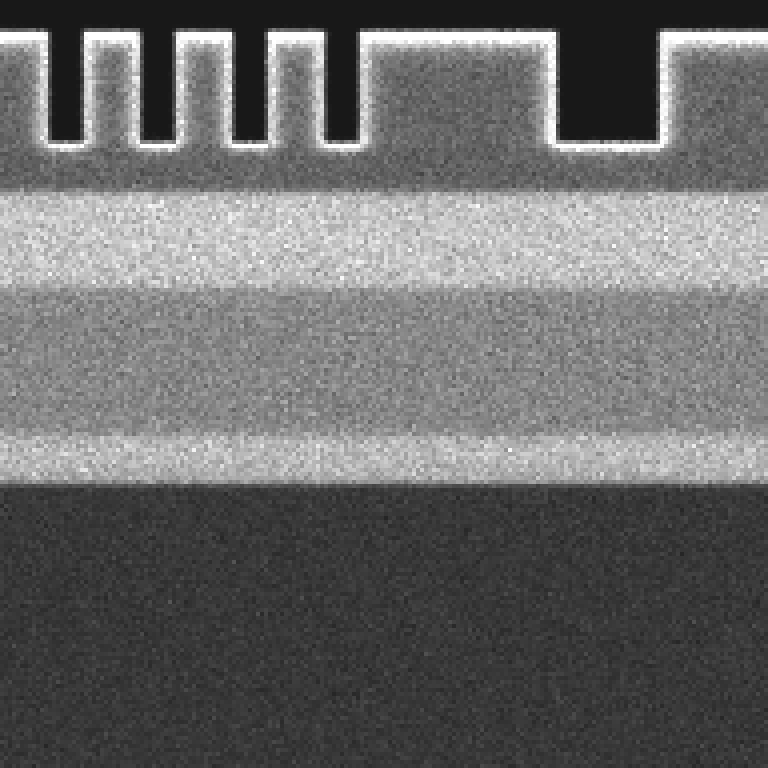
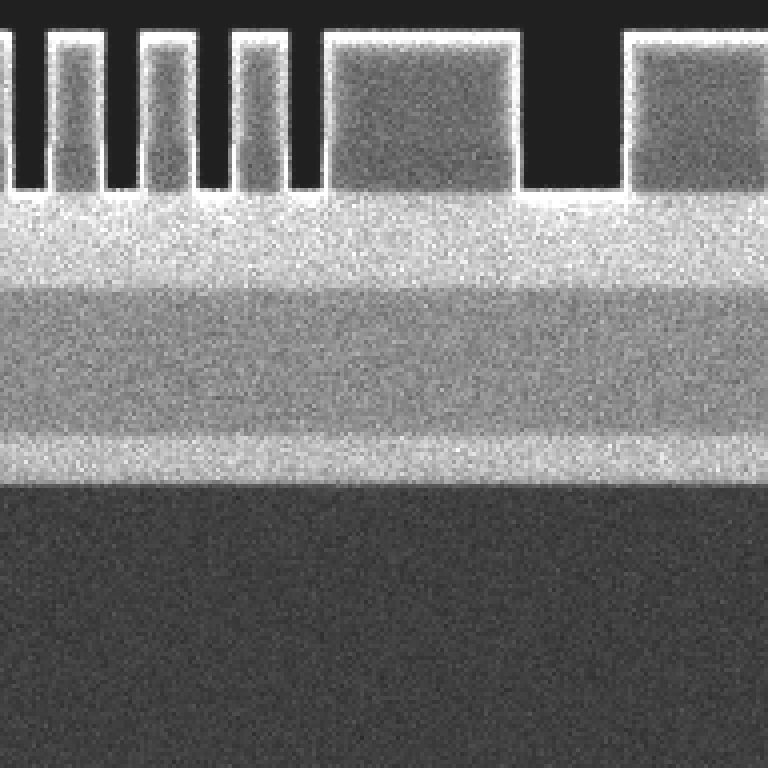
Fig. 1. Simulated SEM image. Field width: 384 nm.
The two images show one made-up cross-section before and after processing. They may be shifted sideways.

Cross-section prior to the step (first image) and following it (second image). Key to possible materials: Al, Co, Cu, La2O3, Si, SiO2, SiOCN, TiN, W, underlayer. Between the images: TiN was removed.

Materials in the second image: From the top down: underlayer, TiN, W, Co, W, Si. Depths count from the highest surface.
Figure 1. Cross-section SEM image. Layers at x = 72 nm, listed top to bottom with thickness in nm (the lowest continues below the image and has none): underlayer 56, TiN 24, W 48, Co 74, W 24, Si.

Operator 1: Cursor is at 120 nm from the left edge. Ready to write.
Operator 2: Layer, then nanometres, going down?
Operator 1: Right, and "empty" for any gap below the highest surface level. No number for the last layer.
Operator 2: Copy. underlayer 56, TiN 24, W 48, Co 74, W 24, Si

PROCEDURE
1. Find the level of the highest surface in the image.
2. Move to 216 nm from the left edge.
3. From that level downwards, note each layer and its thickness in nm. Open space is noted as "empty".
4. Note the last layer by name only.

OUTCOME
underlayer 56, TiN 24, W 48, Co 74, W 24, Si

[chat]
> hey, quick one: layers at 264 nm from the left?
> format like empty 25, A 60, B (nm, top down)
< empty 80, W 48, Co 74, W 24, Si